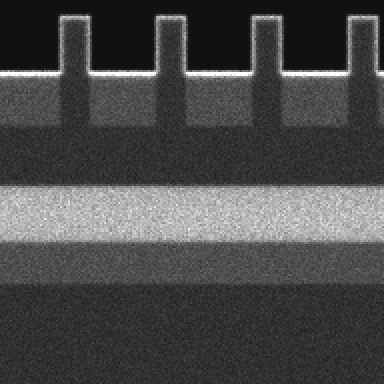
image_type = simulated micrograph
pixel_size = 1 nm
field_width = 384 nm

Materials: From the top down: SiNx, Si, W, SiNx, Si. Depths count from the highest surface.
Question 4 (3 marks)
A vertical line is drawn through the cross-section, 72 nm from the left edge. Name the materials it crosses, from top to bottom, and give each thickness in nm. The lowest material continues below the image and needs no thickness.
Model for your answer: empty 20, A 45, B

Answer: Si 170, W 56, SiNx 42, Si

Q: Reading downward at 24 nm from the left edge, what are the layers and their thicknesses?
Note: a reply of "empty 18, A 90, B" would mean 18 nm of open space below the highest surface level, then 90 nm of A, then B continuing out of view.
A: empty 56, SiNx 54, Si 60, W 56, SiNx 42, Si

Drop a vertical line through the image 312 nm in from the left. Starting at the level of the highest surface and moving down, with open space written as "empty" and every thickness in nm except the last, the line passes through empty 56, SiNx 54, Si 60, W 56, SiNx 42, Si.